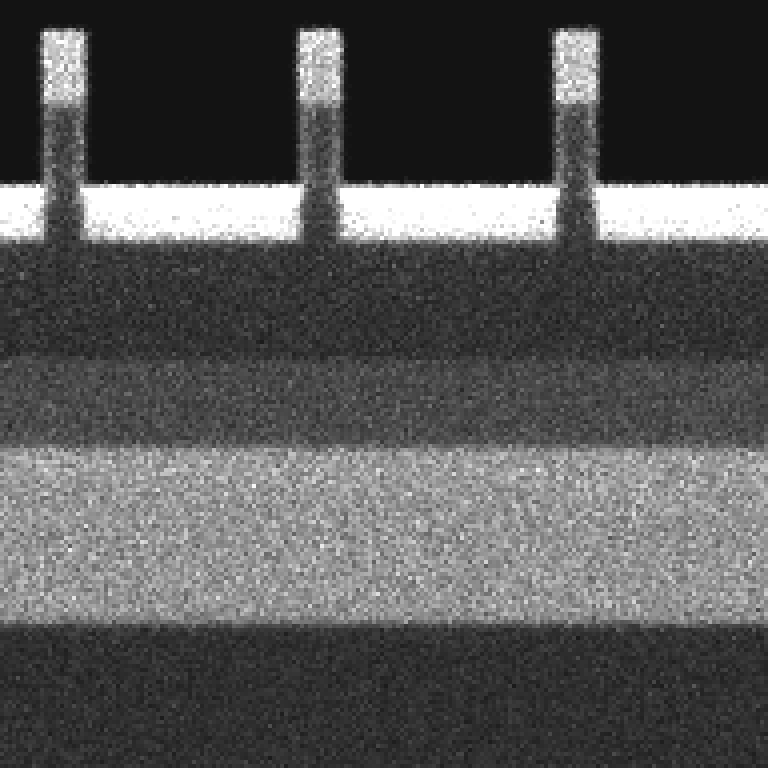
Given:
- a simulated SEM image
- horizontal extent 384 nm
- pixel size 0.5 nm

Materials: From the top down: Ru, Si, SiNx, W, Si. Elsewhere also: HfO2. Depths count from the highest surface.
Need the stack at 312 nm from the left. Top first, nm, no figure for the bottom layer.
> empty 78, HfO2 26, Si 60, SiNx 44, W 88, Si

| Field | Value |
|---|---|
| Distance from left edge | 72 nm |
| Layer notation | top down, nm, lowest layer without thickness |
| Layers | empty 78, HfO2 26, Si 60, SiNx 44, W 88, Si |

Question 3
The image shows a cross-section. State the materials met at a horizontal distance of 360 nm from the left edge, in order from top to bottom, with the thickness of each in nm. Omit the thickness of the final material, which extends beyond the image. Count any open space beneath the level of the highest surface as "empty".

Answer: empty 78, HfO2 26, Si 60, SiNx 44, W 88, Si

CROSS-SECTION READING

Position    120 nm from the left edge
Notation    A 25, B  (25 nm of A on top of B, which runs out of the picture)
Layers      empty 78, HfO2 26, Si 60, SiNx 44, W 88, Si